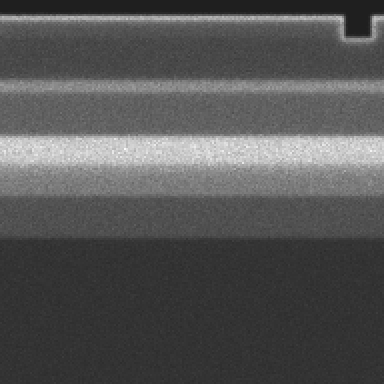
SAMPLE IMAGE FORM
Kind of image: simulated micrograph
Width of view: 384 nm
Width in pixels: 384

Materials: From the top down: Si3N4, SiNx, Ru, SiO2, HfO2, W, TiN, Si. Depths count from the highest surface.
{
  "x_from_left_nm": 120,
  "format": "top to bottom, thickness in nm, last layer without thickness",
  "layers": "Si3N4 22, SiNx 42, Ru 12, SiO2 44, HfO2 28, W 32, TiN 42, Si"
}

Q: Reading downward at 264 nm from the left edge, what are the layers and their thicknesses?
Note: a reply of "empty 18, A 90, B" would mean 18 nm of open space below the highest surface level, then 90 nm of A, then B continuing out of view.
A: Si3N4 22, SiNx 42, Ru 12, SiO2 44, HfO2 28, W 32, TiN 42, Si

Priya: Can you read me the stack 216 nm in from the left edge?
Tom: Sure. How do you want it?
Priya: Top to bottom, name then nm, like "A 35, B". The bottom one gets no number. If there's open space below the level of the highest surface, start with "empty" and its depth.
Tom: Si3N4 22, SiNx 42, Ru 12, SiO2 44, HfO2 28, W 32, TiN 42, Si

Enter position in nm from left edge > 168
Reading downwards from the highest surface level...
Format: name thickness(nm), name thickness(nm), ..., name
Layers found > Si3N4 22, SiNx 42, Ru 12, SiO2 44, HfO2 28, W 32, TiN 42, Si